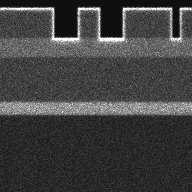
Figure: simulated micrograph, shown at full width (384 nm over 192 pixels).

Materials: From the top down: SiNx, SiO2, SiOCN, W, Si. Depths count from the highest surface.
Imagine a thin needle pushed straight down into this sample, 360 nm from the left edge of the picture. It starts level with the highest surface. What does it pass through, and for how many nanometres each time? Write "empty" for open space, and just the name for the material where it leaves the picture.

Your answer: SiNx 60, SiO2 38, SiOCN 90, W 26, Si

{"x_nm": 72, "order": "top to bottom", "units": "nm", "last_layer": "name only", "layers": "SiNx 60, SiO2 38, SiOCN 90, W 26, Si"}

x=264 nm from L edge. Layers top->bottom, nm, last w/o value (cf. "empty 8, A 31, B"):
SiNx 60, SiO2 38, SiOCN 90, W 26, Si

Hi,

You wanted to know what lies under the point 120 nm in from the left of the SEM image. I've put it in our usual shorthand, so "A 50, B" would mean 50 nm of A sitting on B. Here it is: empty 60, SiO2 38, SiOCN 90, W 26, Si